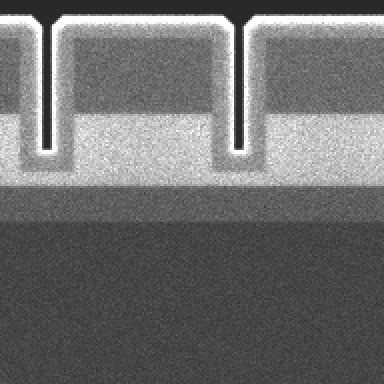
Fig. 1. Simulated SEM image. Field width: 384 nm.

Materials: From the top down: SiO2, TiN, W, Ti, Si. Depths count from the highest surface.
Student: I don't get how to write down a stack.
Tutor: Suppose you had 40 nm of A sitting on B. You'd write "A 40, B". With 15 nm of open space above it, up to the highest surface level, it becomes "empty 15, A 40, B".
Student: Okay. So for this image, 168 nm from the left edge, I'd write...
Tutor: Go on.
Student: SiO2 22, TiN 76, W 72, Ti 36, Si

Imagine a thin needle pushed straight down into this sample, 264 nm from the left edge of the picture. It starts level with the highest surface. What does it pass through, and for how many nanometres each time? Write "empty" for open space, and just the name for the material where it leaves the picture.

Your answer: SiO2 156, W 14, Ti 36, Si